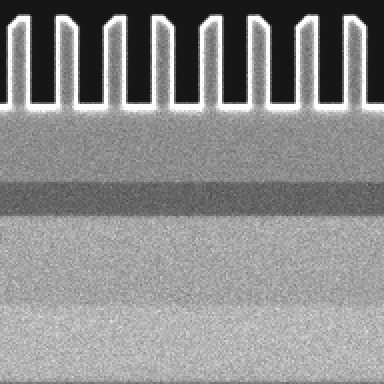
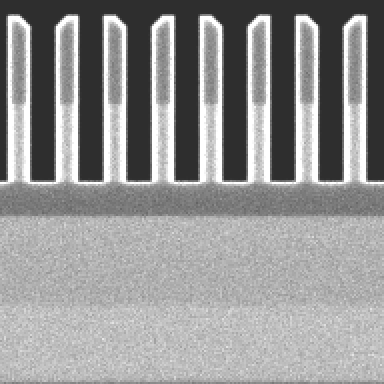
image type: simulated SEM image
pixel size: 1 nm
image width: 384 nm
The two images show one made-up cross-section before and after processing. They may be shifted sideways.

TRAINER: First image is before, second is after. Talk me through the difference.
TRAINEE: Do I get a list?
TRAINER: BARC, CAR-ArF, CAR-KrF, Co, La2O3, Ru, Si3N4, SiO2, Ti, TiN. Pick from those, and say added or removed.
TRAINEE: removed: SiO2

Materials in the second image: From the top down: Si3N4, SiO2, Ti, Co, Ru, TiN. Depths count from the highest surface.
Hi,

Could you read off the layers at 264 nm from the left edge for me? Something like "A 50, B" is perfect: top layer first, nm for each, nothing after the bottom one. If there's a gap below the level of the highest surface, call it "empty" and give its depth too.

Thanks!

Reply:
Si3N4 88, SiO2 78, Ti 34, Co 90, Ru 76, TiN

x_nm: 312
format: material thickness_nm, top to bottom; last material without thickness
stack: empty 6, Si3N4 82, SiO2 78, Ti 34, Co 90, Ru 76, TiN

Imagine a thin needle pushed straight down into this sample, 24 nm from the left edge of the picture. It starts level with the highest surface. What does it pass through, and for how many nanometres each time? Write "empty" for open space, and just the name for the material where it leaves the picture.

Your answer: empty 6, Si3N4 82, SiO2 78, Ti 34, Co 90, Ru 76, TiN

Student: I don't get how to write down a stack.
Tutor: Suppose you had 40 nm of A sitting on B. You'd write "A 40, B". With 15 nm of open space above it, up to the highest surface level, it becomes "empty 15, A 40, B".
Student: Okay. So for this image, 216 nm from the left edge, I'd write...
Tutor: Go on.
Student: empty 6, Si3N4 82, SiO2 78, Ti 34, Co 90, Ru 76, TiN